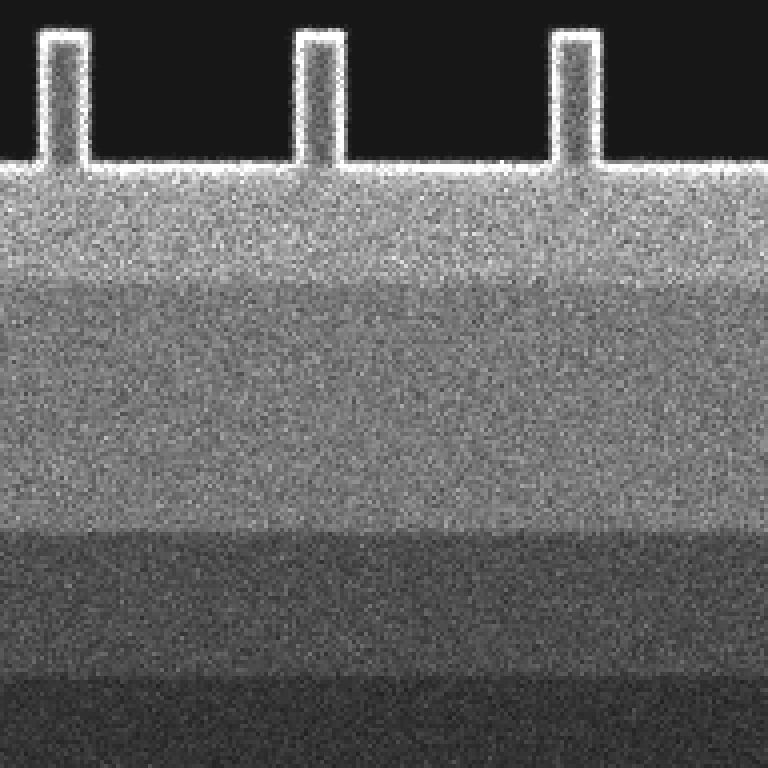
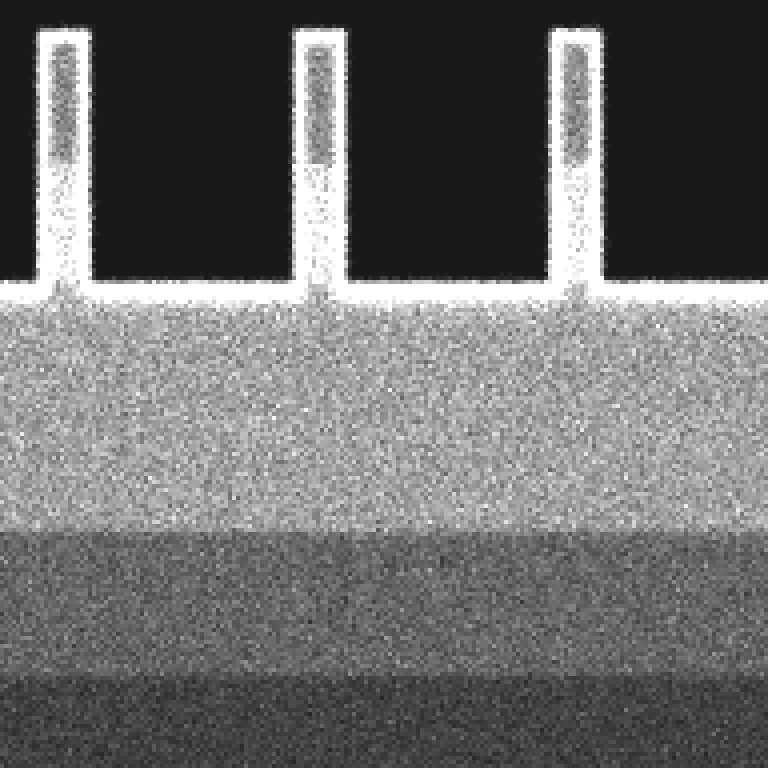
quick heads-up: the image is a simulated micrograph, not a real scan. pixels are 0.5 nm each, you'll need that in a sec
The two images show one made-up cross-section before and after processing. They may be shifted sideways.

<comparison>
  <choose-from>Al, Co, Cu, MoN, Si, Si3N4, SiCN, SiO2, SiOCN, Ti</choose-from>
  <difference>Co removed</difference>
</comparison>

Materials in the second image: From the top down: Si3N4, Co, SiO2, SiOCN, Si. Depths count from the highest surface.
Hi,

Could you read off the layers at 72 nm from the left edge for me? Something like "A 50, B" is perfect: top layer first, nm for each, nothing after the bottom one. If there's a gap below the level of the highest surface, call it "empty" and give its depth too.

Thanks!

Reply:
empty 126, SiO2 124, SiOCN 72, Si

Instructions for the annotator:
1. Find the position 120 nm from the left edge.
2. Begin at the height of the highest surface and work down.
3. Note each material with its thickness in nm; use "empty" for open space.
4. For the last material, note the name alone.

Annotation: empty 126, SiO2 124, SiOCN 72, Si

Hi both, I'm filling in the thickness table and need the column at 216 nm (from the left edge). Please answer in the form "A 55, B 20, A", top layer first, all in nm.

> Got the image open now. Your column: empty 126, SiO2 124, SiOCN 72, Si